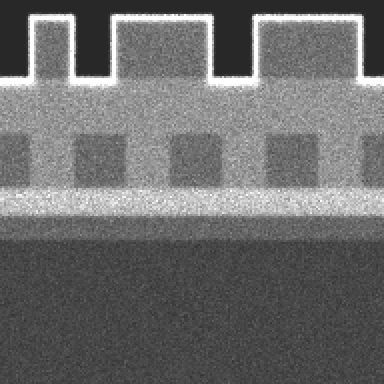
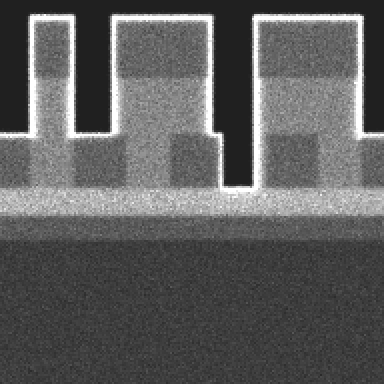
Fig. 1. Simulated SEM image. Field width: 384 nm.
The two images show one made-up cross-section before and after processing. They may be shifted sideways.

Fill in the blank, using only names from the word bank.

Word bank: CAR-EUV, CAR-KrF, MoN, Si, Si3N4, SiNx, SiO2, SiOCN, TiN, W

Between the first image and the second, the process removed SiO2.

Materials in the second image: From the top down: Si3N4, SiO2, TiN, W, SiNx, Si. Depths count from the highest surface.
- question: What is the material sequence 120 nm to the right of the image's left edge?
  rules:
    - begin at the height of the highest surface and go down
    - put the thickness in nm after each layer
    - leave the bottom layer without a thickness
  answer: Si3N4 62, SiO2 56, TiN 54, W 28, SiNx 24, Si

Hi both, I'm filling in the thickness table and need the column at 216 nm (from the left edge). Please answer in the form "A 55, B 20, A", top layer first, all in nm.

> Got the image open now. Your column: empty 118, TiN 54, W 28, SiNx 24, Si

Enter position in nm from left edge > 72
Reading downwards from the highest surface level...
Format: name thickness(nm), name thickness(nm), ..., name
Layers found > Si3N4 62, SiO2 110, W 28, SiNx 24, Si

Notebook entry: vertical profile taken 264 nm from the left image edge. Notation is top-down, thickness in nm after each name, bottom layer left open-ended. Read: Si3N4 62, SiO2 110, W 28, SiNx 24, Si